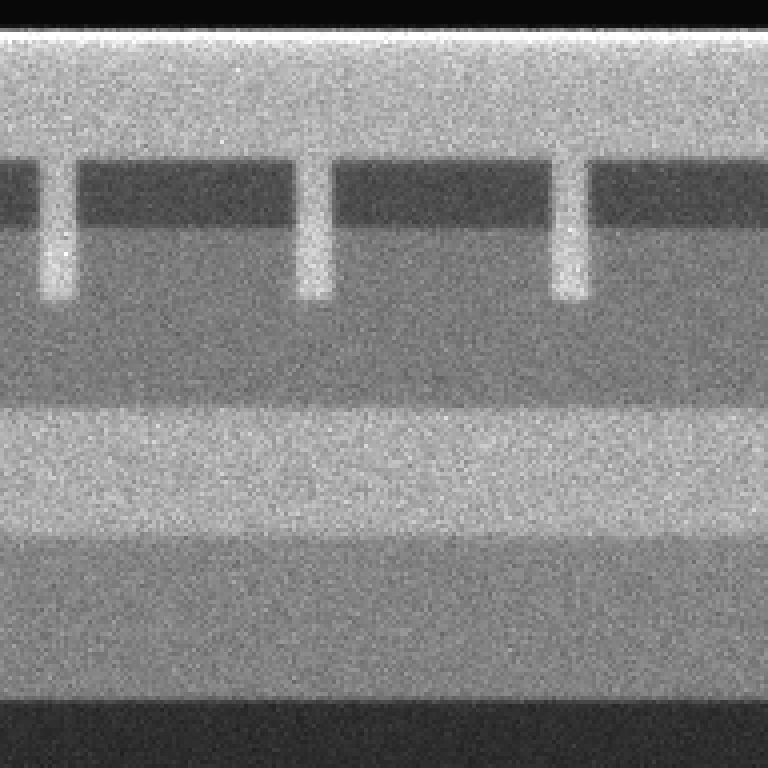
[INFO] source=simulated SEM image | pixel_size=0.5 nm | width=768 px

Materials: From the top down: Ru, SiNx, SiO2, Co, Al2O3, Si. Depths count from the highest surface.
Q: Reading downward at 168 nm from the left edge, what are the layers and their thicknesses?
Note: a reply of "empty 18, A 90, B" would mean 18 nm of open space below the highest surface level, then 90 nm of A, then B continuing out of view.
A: Ru 64, SiNx 34, SiO2 90, Co 64, Al2O3 82, Si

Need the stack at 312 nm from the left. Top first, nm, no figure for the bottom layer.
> Ru 64, SiNx 34, SiO2 90, Co 64, Al2O3 82, Si